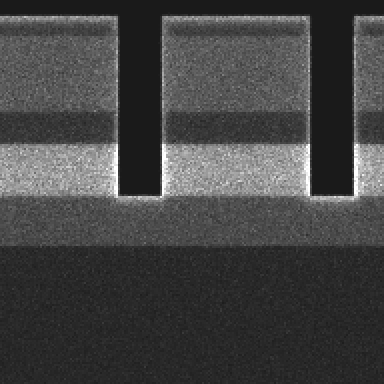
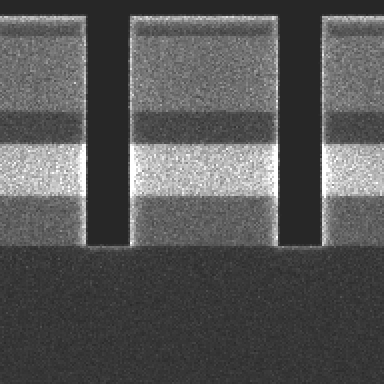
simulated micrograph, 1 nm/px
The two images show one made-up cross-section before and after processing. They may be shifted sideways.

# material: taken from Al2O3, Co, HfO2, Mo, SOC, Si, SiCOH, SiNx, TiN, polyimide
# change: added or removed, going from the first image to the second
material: Al2O3
change: removed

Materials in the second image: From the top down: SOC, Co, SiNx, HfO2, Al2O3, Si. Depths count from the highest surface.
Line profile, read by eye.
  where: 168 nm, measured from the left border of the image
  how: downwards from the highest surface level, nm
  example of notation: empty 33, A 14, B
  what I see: SOC 20, Co 76, SiNx 32, HfO2 52, Al2O3 50, Si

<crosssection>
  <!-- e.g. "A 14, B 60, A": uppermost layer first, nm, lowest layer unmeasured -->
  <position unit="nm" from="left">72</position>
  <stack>SOC 20, Co 76, SiNx 32, HfO2 52, Al2O3 50, Si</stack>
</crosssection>